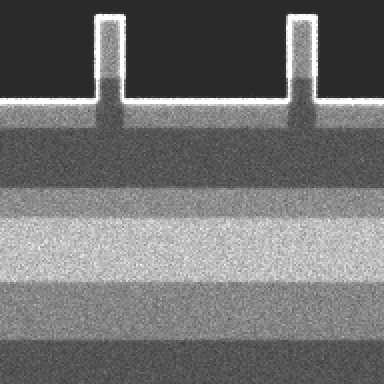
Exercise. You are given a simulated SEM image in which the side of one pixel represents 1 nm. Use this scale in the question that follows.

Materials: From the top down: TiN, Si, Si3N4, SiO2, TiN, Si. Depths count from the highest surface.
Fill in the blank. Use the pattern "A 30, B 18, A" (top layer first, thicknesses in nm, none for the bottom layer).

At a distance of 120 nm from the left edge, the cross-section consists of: TiN 62, Si 110, Si3N4 30, SiO2 64, TiN 58, Si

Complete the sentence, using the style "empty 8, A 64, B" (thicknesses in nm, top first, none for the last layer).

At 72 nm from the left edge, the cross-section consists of empty 84, TiN 28, Si 60, Si3N4 30, SiO2 64, TiN 58, Si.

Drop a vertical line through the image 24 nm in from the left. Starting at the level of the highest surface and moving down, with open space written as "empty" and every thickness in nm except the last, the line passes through empty 84, TiN 28, Si 60, Si3N4 30, SiO2 64, TiN 58, Si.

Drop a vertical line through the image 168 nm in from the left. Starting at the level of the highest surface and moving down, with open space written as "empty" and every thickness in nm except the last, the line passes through empty 84, TiN 28, Si 60, Si3N4 30, SiO2 64, TiN 58, Si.